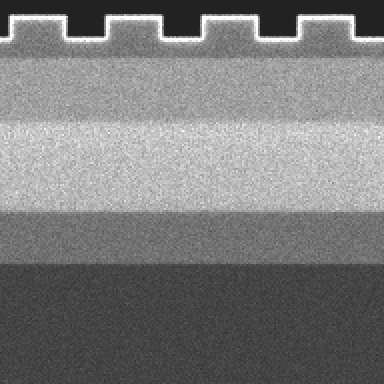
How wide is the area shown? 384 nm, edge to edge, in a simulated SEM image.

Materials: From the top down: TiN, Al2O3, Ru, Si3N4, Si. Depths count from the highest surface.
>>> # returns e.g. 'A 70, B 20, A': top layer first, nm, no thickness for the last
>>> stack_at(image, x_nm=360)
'empty 22, TiN 20, Al2O3 64, Ru 90, Si3N4 52, Si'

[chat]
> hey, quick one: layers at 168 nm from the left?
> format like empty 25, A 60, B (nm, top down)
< empty 22, TiN 20, Al2O3 64, Ru 90, Si3N4 52, Si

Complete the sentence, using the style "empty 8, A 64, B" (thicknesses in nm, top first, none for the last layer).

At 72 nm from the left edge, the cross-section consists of empty 22, TiN 20, Al2O3 64, Ru 90, Si3N4 52, Si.